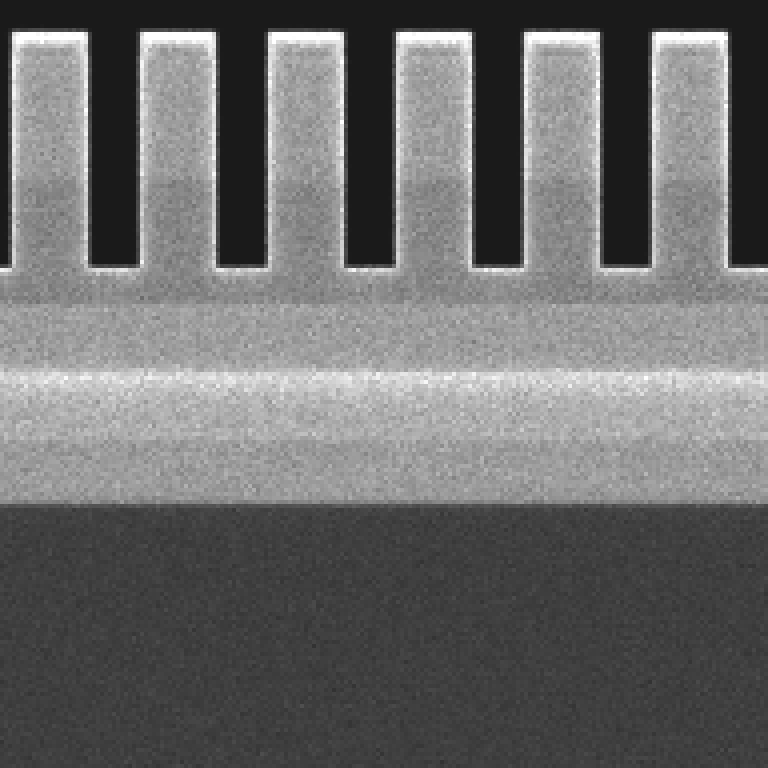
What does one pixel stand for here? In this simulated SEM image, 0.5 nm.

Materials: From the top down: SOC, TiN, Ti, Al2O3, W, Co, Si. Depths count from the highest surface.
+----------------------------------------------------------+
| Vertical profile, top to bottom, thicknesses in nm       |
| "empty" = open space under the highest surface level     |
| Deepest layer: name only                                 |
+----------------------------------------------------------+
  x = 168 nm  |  SOC 12, TiN 62, Ti 62, Al2O3 34, W 34, Co 32, Si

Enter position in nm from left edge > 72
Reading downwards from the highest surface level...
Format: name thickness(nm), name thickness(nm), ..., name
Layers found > SOC 12, TiN 62, Ti 62, Al2O3 34, W 34, Co 32, Si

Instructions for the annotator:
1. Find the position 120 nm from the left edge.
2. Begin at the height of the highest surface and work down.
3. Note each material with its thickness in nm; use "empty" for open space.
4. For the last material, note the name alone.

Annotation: empty 118, Ti 18, Al2O3 34, W 34, Co 32, Si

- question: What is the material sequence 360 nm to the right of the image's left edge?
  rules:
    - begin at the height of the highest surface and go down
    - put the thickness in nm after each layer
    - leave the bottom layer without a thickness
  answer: SOC 12, TiN 62, Ti 62, Al2O3 34, W 34, Co 32, Si